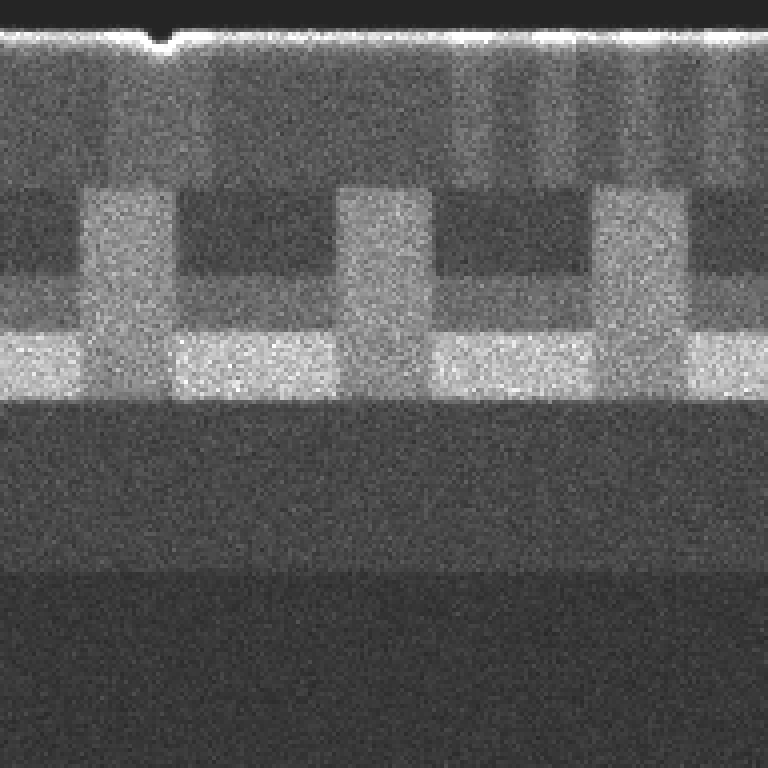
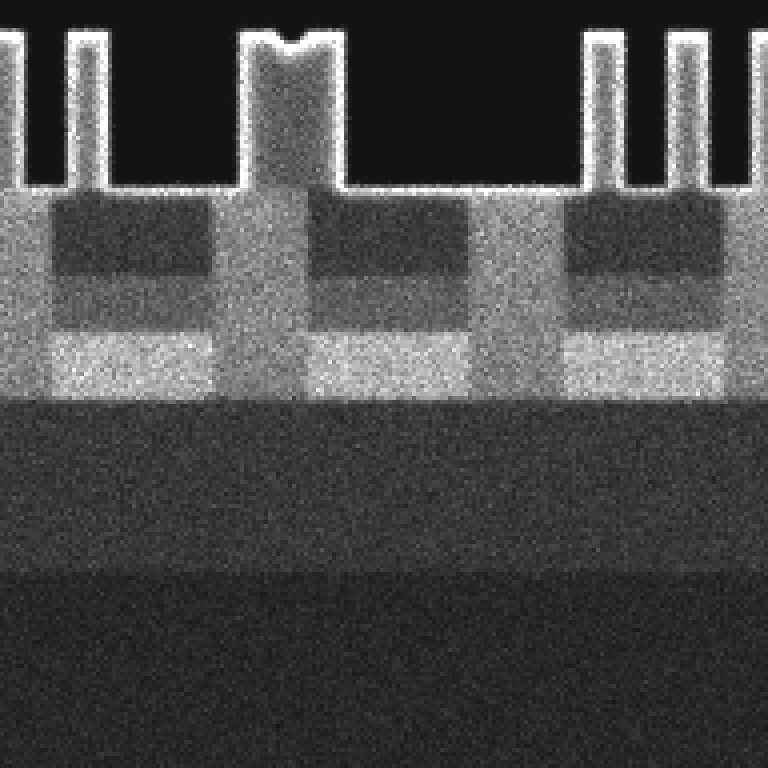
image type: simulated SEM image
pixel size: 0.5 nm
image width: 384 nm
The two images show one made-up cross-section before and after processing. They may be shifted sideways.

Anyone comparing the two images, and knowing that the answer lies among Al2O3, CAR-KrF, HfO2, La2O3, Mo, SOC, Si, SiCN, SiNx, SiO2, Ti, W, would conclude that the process removed SOC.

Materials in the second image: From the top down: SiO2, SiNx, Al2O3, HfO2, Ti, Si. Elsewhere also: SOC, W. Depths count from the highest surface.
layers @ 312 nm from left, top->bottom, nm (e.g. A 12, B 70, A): empty 78, SiNx 44, Al2O3 28, HfO2 34, Ti 86, Si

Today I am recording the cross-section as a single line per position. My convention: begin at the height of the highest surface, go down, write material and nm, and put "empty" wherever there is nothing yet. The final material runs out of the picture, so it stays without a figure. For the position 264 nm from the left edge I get empty 78, W 106, Ti 86, Si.